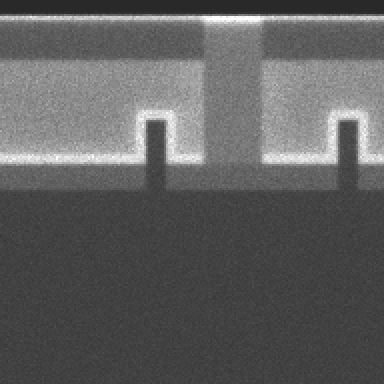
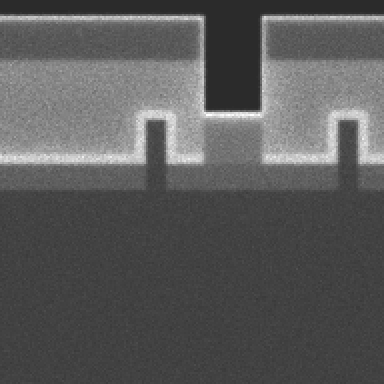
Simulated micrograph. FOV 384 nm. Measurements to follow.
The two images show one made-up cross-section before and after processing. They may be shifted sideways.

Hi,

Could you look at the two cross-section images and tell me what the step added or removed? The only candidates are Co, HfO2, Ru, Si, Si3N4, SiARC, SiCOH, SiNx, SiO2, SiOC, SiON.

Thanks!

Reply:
removed SiO2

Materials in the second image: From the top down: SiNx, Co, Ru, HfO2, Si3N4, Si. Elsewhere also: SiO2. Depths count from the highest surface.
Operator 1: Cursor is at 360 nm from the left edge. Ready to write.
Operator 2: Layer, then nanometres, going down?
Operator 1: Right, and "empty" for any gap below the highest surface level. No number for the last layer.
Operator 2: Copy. SiNx 44, Co 40, Ru 10, HfO2 54, Si3N4 26, Si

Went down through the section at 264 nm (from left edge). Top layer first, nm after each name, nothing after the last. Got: SiNx 44, Co 84, Ru 10, HfO2 10, Si3N4 26, Si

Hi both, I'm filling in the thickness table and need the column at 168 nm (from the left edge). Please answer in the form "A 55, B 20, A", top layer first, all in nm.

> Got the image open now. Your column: SiNx 44, Co 40, Ru 10, HfO2 54, Si3N4 26, Si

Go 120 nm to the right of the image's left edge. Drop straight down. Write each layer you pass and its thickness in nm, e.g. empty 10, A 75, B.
SiNx 44, Co 84, Ru 10, HfO2 10, Si3N4 26, Si